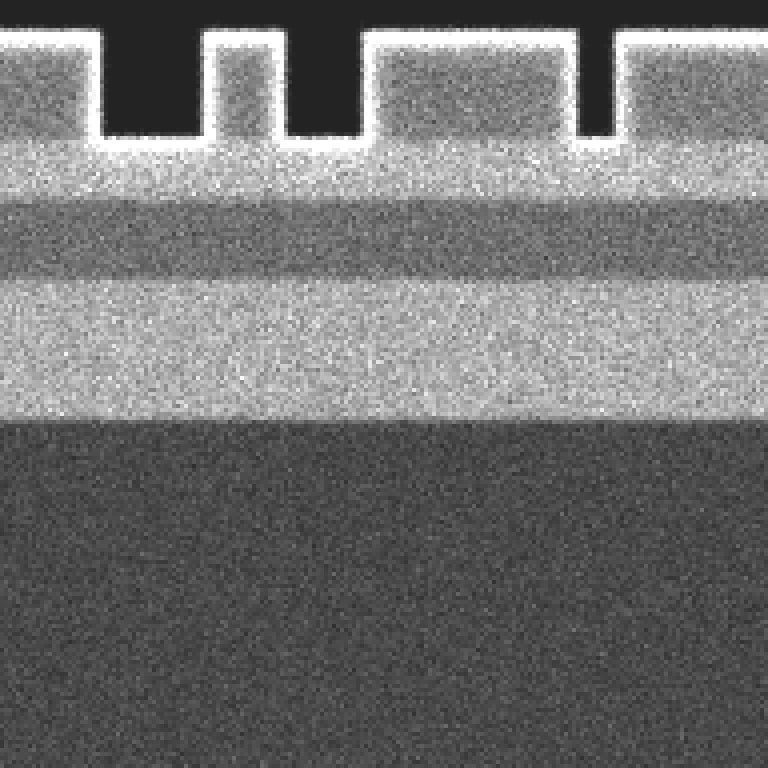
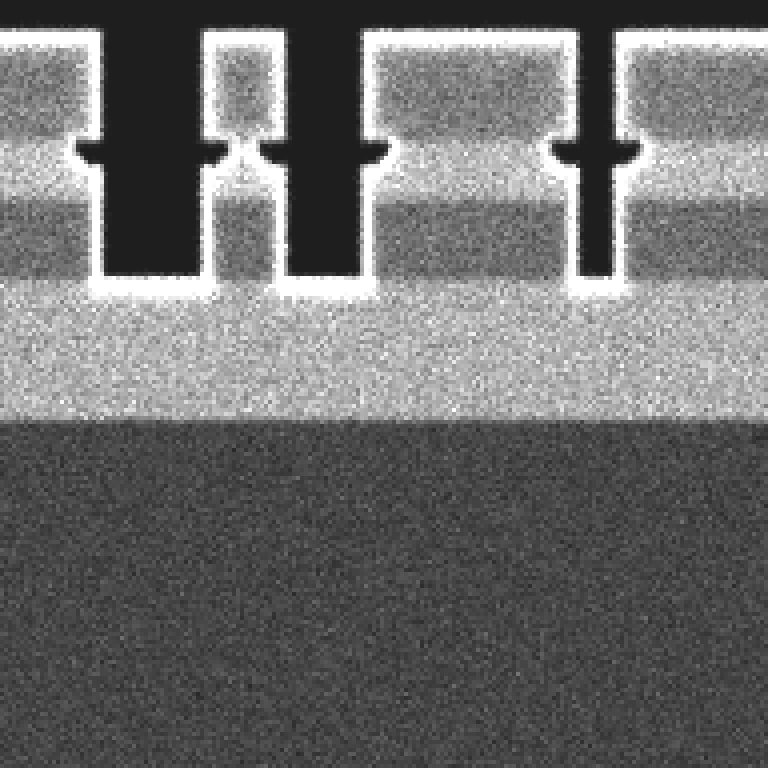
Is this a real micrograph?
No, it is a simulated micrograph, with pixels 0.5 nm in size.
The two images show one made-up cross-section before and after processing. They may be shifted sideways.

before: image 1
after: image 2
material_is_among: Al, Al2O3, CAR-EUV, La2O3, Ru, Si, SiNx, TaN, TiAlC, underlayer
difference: Ru and SiNx, removed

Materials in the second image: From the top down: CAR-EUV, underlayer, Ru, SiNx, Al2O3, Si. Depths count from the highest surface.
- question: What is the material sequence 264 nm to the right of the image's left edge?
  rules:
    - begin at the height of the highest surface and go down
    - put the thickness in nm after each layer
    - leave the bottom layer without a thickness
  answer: CAR-EUV 36, underlayer 18, Ru 30, SiNx 40, Al2O3 70, Si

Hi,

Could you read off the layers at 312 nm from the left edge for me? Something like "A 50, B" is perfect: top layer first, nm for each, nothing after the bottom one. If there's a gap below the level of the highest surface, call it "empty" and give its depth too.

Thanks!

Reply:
CAR-EUV 36, underlayer 18, empty 14, Ru 16, SiNx 40, Al2O3 70, Si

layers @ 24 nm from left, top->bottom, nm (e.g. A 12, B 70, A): CAR-EUV 36, underlayer 18, Ru 30, SiNx 40, Al2O3 70, Si